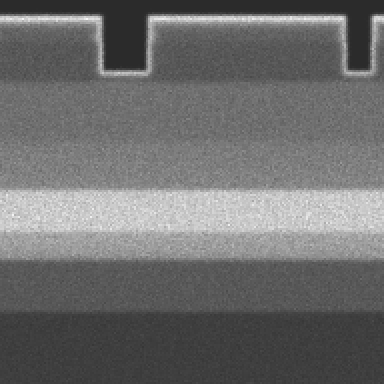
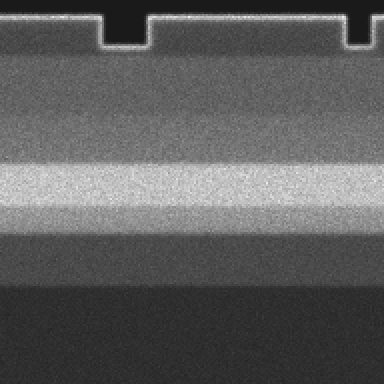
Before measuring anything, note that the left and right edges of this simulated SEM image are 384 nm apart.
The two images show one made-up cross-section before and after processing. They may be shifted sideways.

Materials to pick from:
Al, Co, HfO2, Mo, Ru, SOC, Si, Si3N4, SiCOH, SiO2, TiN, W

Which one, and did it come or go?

SOC - removed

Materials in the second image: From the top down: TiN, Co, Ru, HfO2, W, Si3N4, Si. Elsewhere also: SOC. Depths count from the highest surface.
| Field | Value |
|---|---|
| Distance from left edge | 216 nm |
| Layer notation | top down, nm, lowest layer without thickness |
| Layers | TiN 40, Co 60, Ru 48, HfO2 42, W 28, Si3N4 52, Si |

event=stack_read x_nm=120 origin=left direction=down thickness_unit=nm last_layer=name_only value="empty 30, TiN 10, Co 60, Ru 48, HfO2 42, W 28, Si3N4 52, Si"